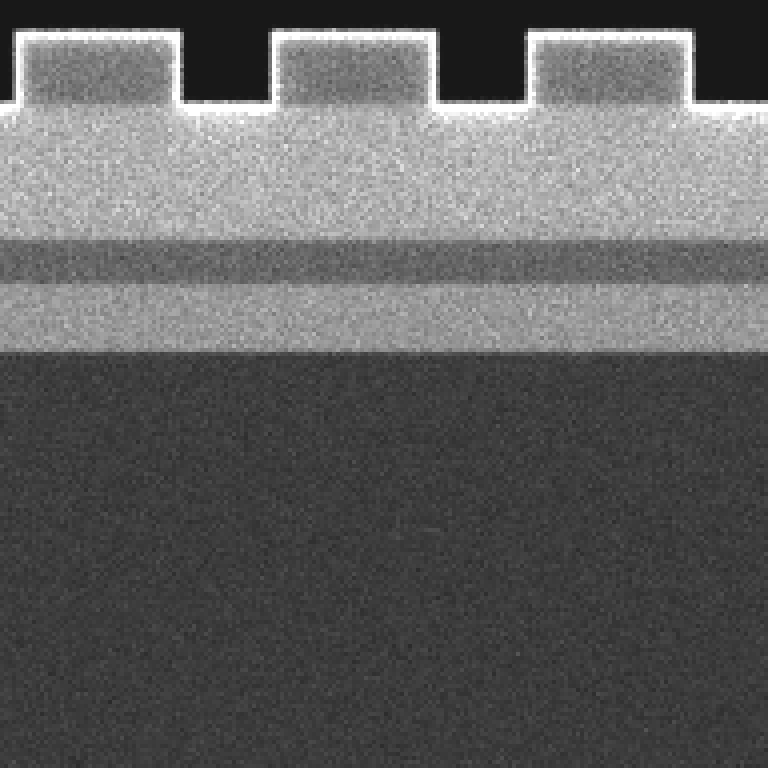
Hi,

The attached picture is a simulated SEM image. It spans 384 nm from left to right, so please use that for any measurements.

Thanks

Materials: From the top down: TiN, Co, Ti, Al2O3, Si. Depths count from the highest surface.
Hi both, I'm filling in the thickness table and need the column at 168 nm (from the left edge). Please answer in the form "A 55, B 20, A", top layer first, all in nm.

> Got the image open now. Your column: TiN 36, Co 68, Ti 22, Al2O3 34, Si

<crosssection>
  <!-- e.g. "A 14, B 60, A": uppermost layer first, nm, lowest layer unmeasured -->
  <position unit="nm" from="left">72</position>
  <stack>TiN 36, Co 68, Ti 22, Al2O3 34, Si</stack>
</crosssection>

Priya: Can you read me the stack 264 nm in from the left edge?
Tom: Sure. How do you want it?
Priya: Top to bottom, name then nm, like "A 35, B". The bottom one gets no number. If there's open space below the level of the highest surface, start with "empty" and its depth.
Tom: TiN 36, Co 68, Ti 22, Al2O3 34, Si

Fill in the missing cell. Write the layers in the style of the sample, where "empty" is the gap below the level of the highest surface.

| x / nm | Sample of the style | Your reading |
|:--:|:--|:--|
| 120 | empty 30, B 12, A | empty 36, Co 68, Ti 22, Al2O3 34, Si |